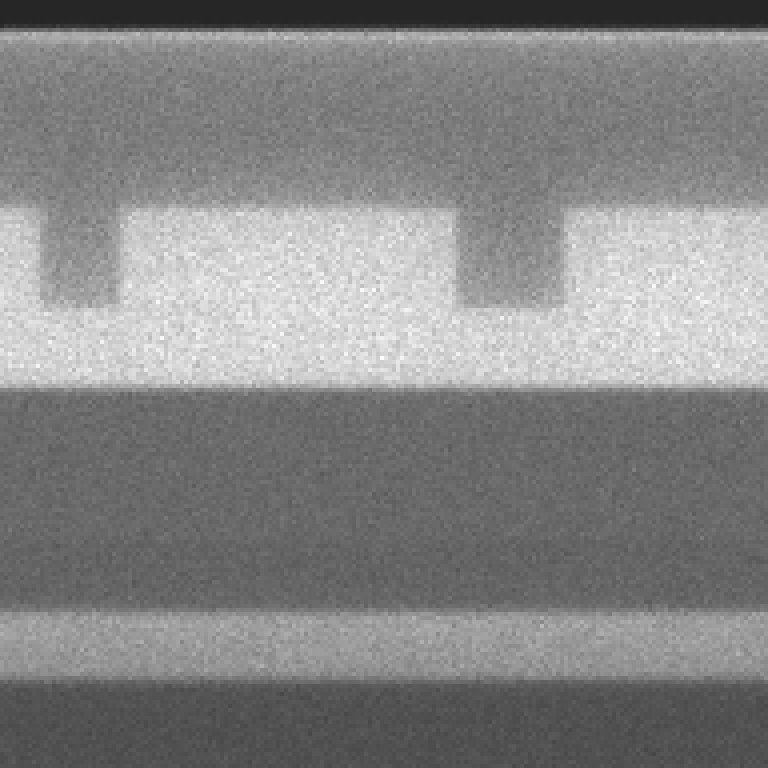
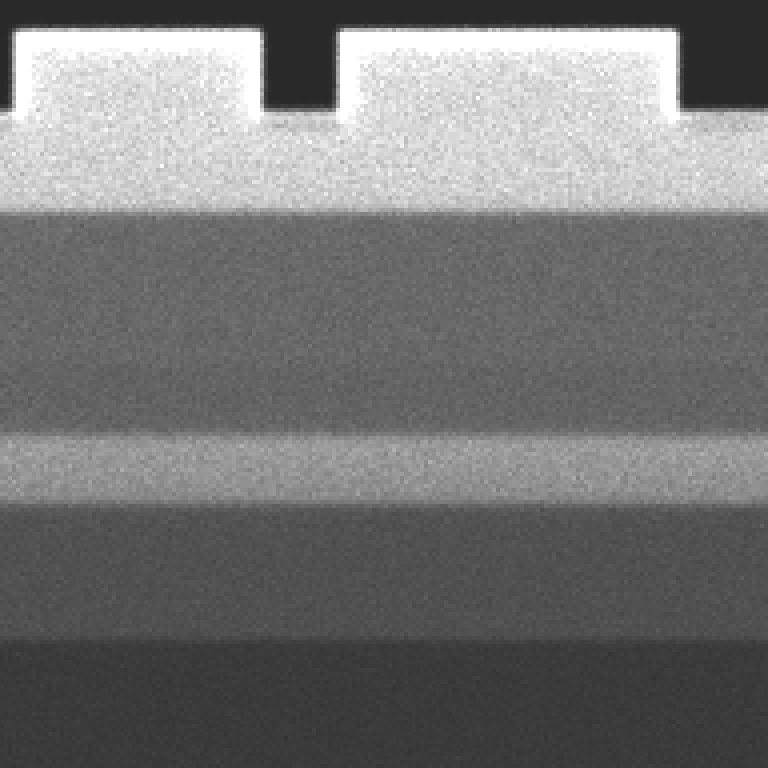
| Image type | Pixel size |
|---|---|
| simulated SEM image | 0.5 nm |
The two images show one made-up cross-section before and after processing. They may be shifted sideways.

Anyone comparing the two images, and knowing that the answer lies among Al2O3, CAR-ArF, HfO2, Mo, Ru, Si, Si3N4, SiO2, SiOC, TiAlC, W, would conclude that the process removed Ru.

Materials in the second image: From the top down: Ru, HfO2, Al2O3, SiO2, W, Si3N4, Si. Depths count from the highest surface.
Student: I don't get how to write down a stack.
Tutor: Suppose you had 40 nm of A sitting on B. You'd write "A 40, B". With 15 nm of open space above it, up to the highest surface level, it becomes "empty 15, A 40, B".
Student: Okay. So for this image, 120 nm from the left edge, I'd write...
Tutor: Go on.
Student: HfO2 90, Al2O3 76, SiO2 36, W 34, Si3N4 68, Si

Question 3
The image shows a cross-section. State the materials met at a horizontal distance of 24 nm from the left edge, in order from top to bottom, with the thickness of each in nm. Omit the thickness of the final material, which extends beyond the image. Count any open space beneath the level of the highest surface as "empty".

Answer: HfO2 90, Al2O3 76, SiO2 36, W 34, Si3N4 68, Si